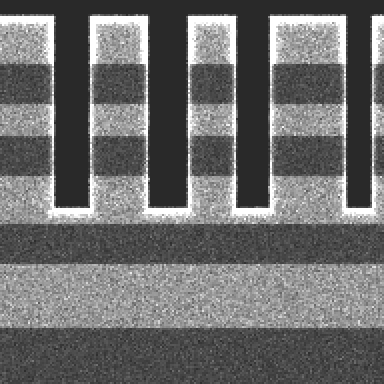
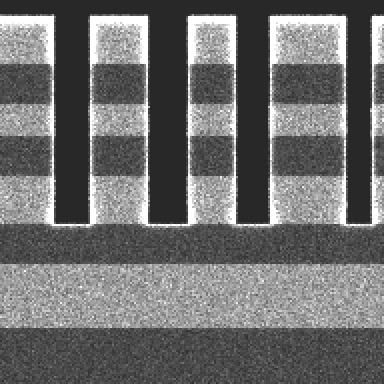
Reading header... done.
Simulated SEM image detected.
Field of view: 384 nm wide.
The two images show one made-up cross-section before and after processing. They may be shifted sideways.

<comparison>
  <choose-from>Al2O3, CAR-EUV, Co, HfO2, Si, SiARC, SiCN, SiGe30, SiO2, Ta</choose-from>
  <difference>SiO2 removed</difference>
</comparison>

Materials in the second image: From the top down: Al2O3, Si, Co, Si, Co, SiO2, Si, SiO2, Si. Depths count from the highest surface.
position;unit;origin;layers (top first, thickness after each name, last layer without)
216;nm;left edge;Al2O3 48, Si 40, Co 32, Si 40, Co 32, SiO2 16, Si 40, SiO2 64, Si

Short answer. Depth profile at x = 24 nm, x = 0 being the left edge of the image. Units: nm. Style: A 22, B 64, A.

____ Al2O3 48, Si 40, Co 32, Si 40, Co 32, SiO2 16, Si 40, SiO2 64, Si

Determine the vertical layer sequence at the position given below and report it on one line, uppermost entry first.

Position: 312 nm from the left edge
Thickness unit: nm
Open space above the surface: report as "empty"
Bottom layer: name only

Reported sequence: Al2O3 48, Si 40, Co 32, Si 40, Co 32, SiO2 16, Si 40, SiO2 64, Si